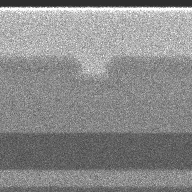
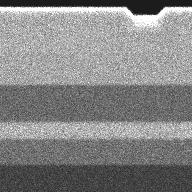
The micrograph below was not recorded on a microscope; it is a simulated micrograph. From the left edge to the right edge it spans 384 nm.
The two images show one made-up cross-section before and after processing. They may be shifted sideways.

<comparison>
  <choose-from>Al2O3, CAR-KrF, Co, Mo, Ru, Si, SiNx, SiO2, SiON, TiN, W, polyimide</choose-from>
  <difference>W removed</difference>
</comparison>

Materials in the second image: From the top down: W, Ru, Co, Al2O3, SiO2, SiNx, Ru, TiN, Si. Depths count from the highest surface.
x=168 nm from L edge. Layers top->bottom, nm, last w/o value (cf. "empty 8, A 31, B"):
Ru 10, Co 24, Al2O3 56, SiO2 64, SiNx 74, Ru 34, TiN 52, Si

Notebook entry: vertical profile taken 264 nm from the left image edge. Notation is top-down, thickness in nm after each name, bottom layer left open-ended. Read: empty 14, Ru 32, Co 24, Al2O3 20, SiO2 64, SiNx 74, Ru 34, TiN 52, Si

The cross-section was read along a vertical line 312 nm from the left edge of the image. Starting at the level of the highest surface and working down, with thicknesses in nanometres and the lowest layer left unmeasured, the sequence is empty 16, W 20, Ru 10, Co 24, Al2O3 20, SiO2 64, SiNx 74, Ru 34, TiN 52, Si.